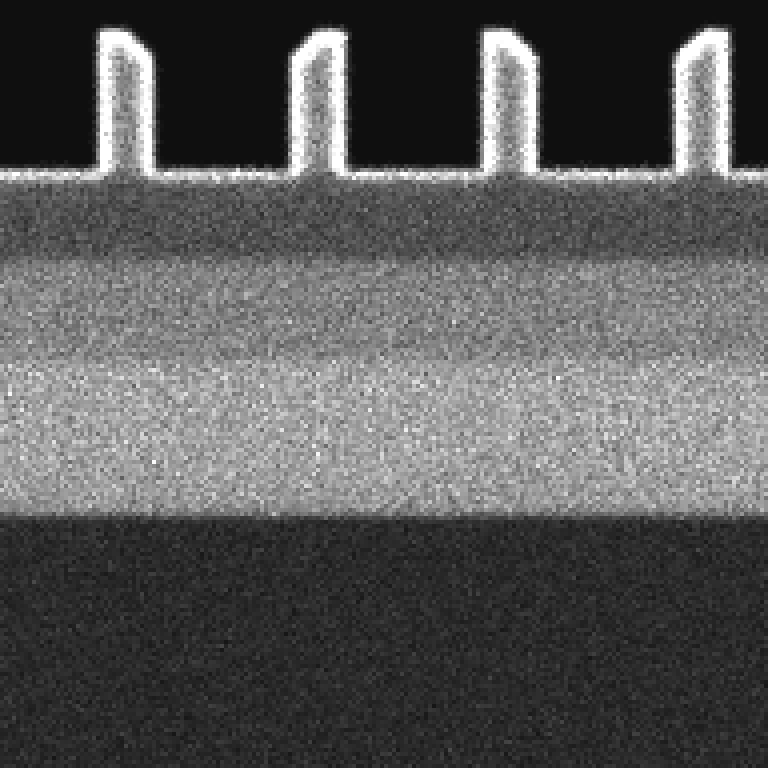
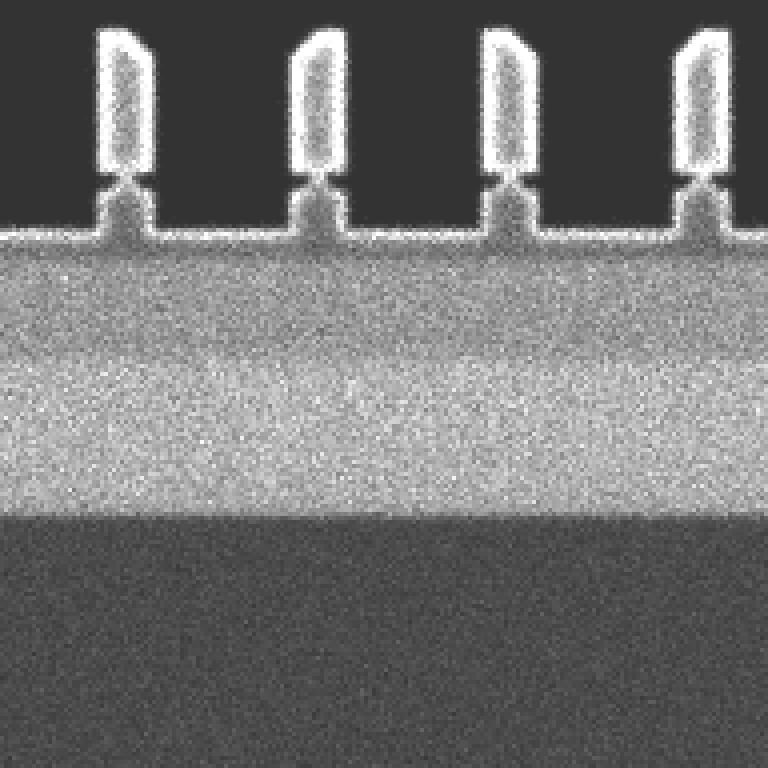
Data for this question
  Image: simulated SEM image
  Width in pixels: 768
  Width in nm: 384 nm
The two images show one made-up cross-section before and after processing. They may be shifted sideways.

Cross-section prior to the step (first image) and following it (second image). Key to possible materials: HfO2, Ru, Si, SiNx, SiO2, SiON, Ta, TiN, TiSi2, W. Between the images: TiN was removed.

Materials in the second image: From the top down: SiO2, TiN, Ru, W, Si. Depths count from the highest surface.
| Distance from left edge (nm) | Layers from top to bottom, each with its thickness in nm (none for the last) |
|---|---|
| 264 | empty 10, SiO2 60, empty 10, TiN 34, Ru 50, W 78, Si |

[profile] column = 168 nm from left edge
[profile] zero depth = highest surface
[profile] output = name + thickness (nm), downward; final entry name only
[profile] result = SiO2 70, empty 10, TiN 34, Ru 50, W 78, Si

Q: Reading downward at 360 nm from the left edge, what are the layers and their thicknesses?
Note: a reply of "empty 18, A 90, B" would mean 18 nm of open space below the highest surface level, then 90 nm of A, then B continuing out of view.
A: SiO2 70, empty 10, TiN 34, Ru 50, W 78, Si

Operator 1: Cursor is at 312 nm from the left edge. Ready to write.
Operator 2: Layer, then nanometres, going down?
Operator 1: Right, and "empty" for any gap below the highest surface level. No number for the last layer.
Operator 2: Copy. empty 100, TiN 14, Ru 50, W 78, Si